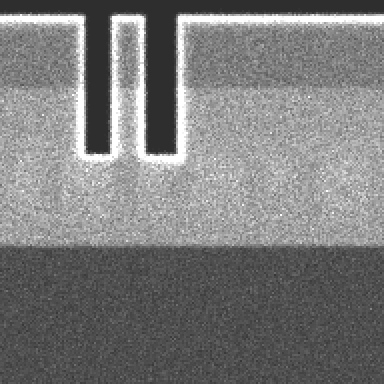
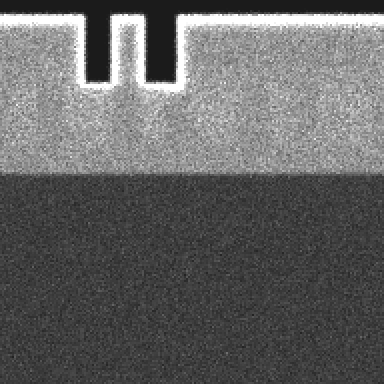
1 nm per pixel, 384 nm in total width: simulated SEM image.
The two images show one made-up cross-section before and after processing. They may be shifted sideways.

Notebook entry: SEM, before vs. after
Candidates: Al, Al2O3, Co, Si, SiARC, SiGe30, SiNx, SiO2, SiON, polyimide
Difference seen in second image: SiARC removed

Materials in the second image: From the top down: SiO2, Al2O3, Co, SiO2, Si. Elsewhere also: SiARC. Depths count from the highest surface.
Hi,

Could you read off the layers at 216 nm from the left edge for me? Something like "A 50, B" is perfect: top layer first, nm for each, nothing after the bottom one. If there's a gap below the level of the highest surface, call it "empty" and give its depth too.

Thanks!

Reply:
SiO2 50, Al2O3 18, Co 64, SiO2 26, Si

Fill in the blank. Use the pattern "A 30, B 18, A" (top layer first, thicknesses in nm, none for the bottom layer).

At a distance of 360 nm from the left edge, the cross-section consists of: SiO2 50, Al2O3 18, Co 64, SiO2 26, Si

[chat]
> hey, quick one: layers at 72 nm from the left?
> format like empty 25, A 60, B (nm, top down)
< SiO2 50, Al2O3 18, Co 64, SiO2 26, Si